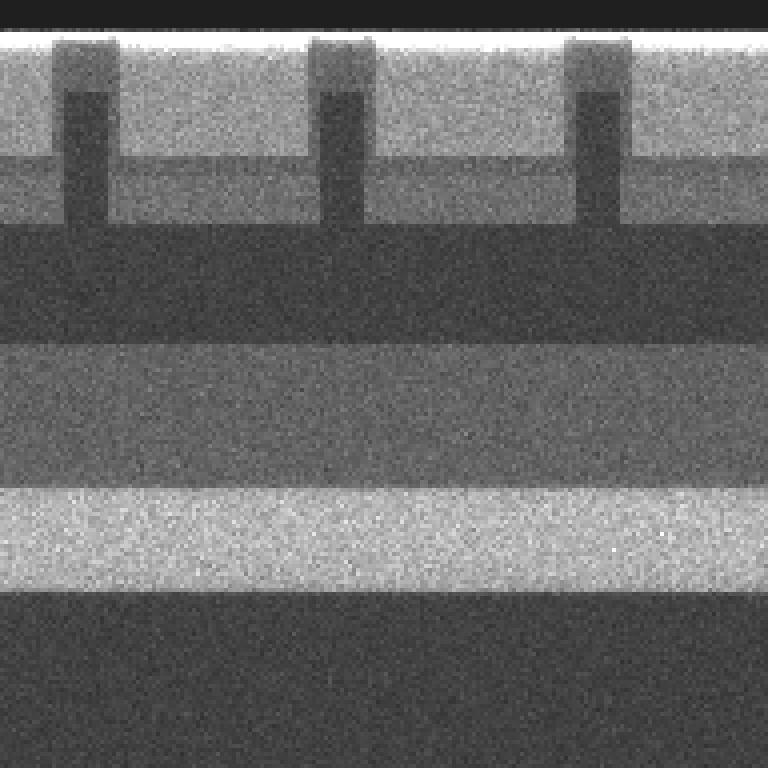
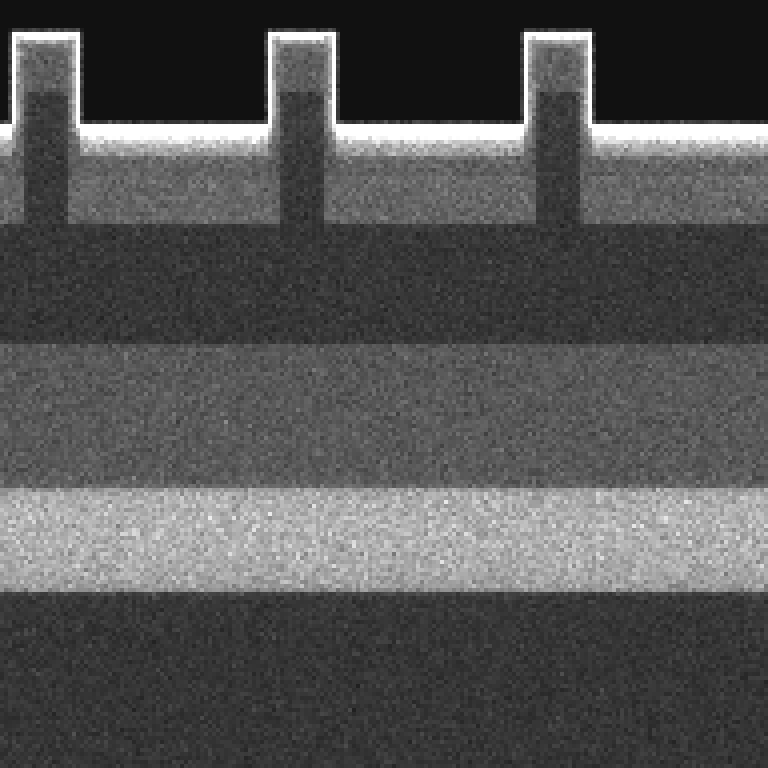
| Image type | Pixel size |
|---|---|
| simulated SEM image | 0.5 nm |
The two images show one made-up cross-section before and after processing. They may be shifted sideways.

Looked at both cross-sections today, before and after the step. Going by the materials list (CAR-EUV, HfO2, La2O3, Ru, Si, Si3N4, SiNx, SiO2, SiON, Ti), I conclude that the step removed SiO2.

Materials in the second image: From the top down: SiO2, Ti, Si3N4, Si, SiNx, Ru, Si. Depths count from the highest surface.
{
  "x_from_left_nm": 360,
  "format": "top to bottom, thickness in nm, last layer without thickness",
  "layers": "empty 46, SiO2 16, Ti 10, Si3N4 24, Si 60, SiNx 72, Ru 52, Si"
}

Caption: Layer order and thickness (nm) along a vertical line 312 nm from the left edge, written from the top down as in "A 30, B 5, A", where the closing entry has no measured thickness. empty 46, SiO2 16, Ti 10, Si3N4 24, Si 60, SiNx 72, Ru 52, Si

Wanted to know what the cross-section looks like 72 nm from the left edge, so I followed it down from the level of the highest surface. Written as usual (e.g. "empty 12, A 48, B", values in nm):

empty 46, SiO2 16, Ti 10, Si3N4 24, Si 60, SiNx 72, Ru 52, Si